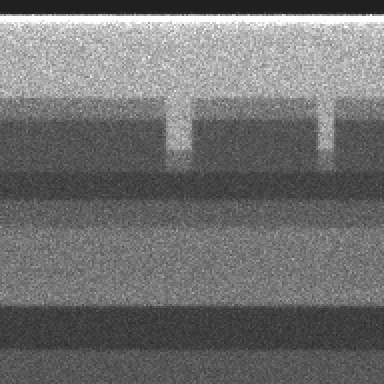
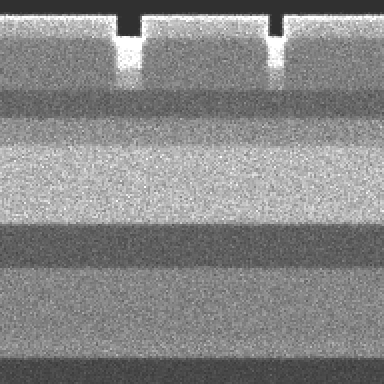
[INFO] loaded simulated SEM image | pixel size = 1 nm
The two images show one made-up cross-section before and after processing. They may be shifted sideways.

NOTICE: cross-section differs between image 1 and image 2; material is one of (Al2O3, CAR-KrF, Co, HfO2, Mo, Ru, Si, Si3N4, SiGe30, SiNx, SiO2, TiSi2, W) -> removed: HfO2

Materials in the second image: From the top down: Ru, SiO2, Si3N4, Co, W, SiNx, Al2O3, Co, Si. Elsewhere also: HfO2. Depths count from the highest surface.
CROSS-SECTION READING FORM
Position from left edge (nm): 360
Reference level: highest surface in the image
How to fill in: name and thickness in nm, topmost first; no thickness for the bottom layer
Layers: Ru 22, SiO2 52, Si3N4 28, Co 28, W 78, SiNx 44, Al2O3 72, Co 18, Si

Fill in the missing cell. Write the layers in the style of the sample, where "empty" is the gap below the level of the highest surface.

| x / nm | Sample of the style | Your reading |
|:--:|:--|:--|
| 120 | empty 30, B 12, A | empty 22, HfO2 30, Ru 22, Si3N4 28, Co 28, W 78, SiNx 44, Al2O3 72, Co 18, Si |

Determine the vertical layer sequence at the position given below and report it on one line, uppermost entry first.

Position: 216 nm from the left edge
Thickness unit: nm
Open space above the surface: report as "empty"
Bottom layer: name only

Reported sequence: Ru 22, SiO2 52, Si3N4 28, Co 28, W 78, SiNx 44, Al2O3 72, Co 18, Si